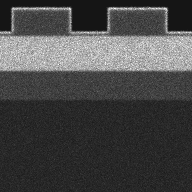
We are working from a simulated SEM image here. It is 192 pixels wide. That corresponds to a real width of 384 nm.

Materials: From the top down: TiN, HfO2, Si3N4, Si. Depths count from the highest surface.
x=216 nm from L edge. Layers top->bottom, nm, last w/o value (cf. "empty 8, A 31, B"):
TiN 56, HfO2 70, Si3N4 58, Si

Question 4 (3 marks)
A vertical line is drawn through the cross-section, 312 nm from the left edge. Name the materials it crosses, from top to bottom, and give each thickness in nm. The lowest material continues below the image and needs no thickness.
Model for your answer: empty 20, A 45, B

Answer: TiN 56, HfO2 70, Si3N4 58, Si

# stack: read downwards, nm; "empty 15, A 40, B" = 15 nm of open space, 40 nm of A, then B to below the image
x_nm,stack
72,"TiN 56, HfO2 70, Si3N4 58, Si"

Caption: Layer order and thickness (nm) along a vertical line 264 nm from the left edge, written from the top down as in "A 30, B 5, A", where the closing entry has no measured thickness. TiN 56, HfO2 70, Si3N4 58, Si